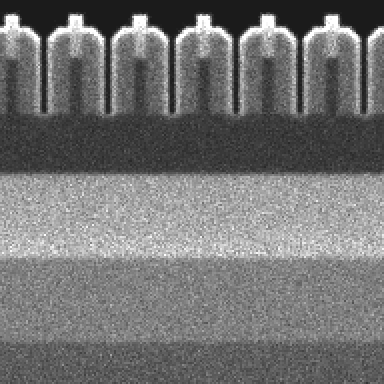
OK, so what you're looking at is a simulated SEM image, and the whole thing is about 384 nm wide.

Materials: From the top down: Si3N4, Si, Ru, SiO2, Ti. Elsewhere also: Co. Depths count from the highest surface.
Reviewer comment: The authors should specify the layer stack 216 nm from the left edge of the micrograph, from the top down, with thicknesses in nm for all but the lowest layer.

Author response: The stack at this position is empty 12, Si3N4 86, Si 60, Ru 84, SiO2 84, Ti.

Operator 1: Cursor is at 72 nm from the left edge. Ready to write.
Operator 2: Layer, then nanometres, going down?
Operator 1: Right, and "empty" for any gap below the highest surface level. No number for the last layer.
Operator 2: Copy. Co 42, Si 116, Ru 84, SiO2 84, Ti